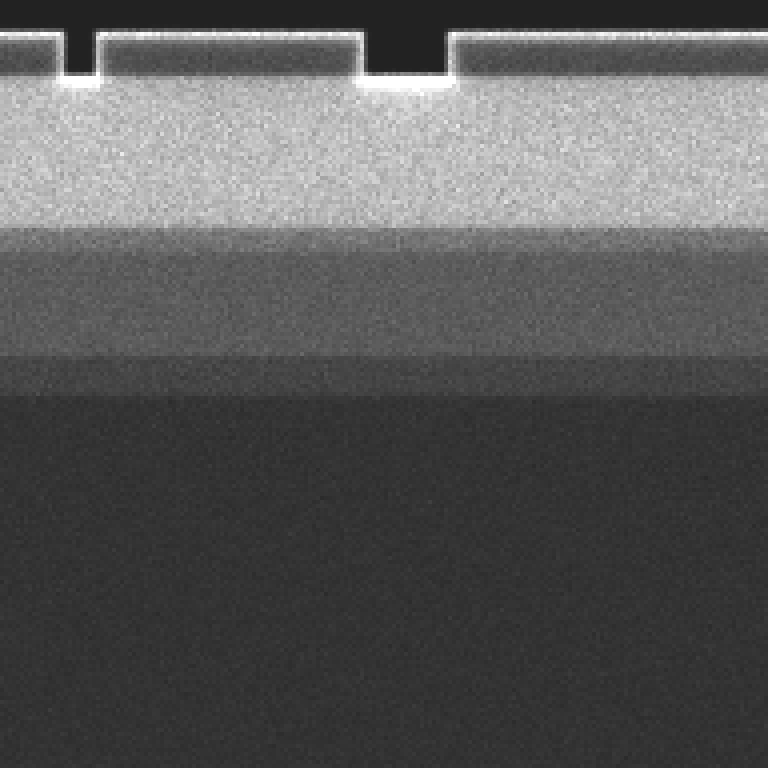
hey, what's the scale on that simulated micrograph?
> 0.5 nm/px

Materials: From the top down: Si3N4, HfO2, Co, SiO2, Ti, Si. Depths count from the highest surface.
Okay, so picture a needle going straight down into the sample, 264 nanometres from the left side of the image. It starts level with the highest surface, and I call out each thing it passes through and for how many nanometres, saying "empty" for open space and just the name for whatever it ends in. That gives Si3N4 22, HfO2 76, Co 12, SiO2 52, Ti 20, Si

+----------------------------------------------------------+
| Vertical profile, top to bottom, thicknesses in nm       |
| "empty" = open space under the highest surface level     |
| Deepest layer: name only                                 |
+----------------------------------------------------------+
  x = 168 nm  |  Si3N4 22, HfO2 76, Co 12, SiO2 52, Ti 20, Si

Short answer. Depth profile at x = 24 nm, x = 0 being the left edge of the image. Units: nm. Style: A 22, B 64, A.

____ Si3N4 22, HfO2 76, Co 12, SiO2 52, Ti 20, Si